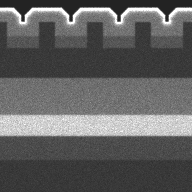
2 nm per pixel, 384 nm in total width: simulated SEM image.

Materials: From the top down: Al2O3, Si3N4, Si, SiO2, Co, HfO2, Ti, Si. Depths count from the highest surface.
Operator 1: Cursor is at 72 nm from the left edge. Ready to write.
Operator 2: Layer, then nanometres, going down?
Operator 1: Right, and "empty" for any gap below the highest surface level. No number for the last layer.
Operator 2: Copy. Al2O3 56, Si3N4 24, Si 60, SiO2 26, Co 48, HfO2 42, Ti 48, Si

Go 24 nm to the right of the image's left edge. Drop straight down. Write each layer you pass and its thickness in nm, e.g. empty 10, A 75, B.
Al2O3 56, Si3N4 24, Si 60, SiO2 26, Co 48, HfO2 42, Ti 48, Si